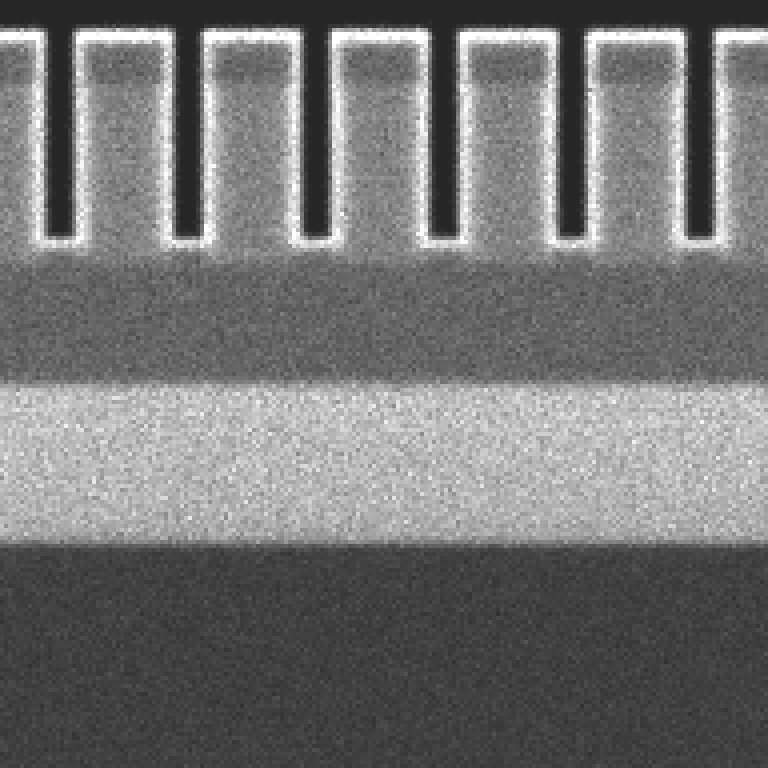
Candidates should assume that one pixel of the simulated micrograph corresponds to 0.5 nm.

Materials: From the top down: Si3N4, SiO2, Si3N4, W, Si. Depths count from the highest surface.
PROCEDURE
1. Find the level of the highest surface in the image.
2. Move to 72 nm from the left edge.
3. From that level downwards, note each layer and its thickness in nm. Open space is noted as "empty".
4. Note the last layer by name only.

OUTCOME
Si3N4 26, SiO2 90, Si3N4 60, W 80, Si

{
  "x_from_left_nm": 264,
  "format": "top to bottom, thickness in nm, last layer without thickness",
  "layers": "Si3N4 26, SiO2 90, Si3N4 60, W 80, Si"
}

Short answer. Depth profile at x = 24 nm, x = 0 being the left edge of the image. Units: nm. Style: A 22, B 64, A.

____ empty 104, Si3N4 72, W 80, Si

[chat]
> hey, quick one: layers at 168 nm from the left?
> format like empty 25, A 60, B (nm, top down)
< Si3N4 26, SiO2 90, Si3N4 60, W 80, Si